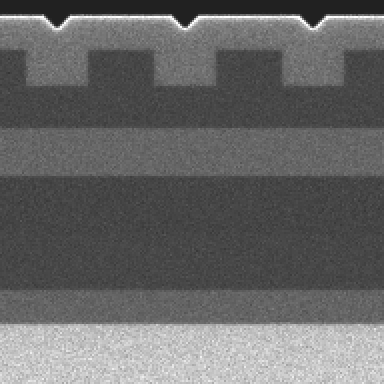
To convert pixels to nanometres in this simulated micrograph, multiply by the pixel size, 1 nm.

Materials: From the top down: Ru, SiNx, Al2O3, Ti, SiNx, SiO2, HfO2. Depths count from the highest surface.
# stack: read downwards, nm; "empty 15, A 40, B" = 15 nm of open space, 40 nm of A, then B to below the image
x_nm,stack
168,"Ru 70, SiNx 42, Al2O3 48, Ti 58, SiNx 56, SiO2 34, HfO2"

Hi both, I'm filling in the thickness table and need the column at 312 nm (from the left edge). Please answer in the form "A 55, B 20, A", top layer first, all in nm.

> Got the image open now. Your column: empty 12, Ru 58, SiNx 42, Al2O3 48, Ti 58, SiNx 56, SiO2 34, HfO2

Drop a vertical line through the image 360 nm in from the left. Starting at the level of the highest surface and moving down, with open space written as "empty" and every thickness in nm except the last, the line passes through Ru 34, SiNx 78, Al2O3 48, Ti 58, SiNx 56, SiO2 34, HfO2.